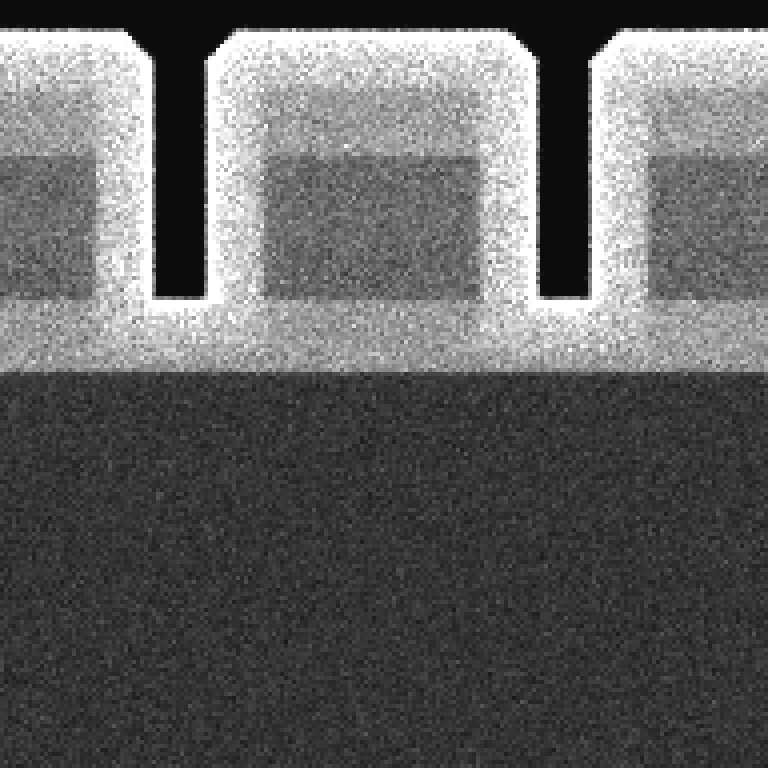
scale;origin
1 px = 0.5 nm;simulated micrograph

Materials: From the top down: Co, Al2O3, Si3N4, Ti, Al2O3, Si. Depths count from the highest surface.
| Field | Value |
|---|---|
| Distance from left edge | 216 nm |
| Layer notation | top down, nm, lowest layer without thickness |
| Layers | Co 28, Al2O3 34, Si3N4 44, Ti 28, Al2O3 36, Si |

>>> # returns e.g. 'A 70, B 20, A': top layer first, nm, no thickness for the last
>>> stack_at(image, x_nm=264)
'empty 12, Co 150, Al2O3 8, Si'